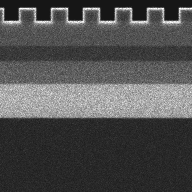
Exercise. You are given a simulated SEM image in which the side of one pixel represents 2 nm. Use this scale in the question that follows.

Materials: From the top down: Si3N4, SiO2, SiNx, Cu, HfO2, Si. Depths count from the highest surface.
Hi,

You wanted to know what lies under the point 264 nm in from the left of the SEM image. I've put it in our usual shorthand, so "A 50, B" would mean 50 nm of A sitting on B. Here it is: empty 26, SiO2 50, SiNx 30, Cu 46, HfO2 68, Si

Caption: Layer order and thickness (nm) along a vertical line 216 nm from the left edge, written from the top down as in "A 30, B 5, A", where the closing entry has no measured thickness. empty 26, SiO2 50, SiNx 30, Cu 46, HfO2 68, Si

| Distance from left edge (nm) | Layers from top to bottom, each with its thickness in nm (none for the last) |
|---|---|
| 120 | Si3N4 26, SiO2 50, SiNx 30, Cu 46, HfO2 68, Si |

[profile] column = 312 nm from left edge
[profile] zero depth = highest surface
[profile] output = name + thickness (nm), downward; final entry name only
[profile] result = Si3N4 26, SiO2 50, SiNx 30, Cu 46, HfO2 68, Si